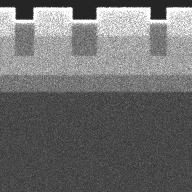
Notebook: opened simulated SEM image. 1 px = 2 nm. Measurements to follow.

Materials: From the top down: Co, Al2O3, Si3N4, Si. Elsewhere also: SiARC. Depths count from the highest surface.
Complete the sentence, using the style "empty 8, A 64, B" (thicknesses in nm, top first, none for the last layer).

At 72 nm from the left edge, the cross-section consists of Co 56, Al2O3 78, Si3N4 34, Si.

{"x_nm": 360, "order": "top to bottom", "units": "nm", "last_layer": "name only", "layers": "Co 56, Al2O3 78, Si3N4 34, Si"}